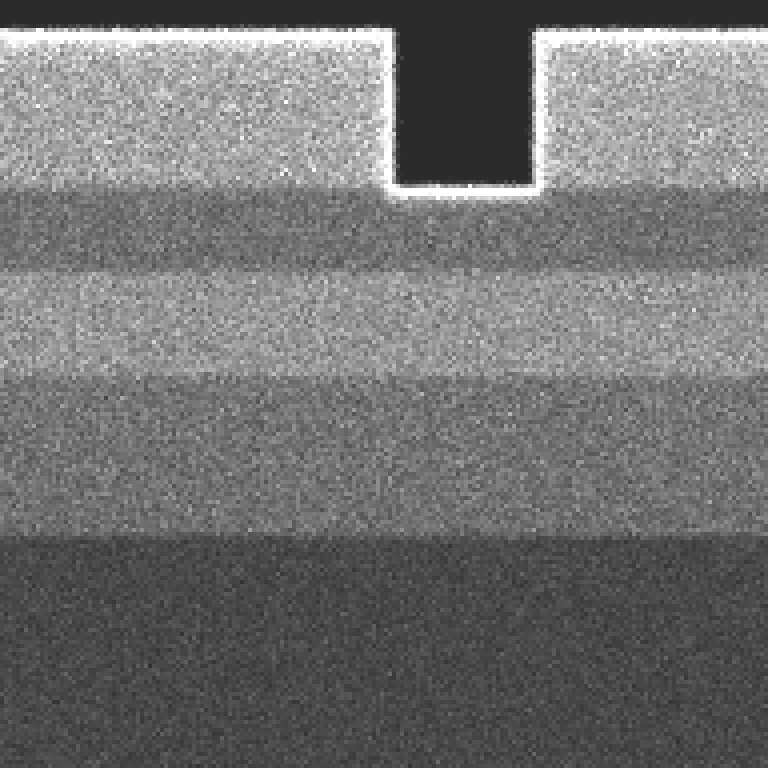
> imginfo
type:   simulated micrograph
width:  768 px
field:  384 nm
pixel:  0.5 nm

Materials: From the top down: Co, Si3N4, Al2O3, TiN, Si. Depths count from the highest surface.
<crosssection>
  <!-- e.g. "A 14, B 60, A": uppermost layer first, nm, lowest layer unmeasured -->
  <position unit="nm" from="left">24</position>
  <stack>Co 78, Si3N4 42, Al2O3 52, TiN 80, Si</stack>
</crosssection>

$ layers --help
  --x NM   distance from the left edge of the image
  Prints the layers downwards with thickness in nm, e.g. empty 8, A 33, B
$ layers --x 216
empty 78, Si3N4 42, Al2O3 52, TiN 80, Si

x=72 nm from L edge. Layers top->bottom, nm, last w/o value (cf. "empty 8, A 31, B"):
Co 78, Si3N4 42, Al2O3 52, TiN 80, Si